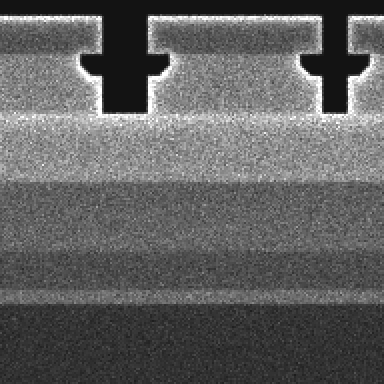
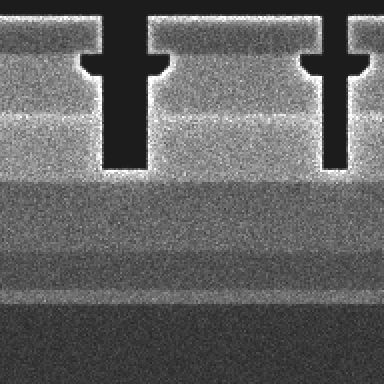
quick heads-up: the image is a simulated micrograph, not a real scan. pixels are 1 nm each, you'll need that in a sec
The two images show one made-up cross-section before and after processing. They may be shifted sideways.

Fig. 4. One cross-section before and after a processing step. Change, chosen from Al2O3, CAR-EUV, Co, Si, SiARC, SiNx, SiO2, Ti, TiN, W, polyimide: W removed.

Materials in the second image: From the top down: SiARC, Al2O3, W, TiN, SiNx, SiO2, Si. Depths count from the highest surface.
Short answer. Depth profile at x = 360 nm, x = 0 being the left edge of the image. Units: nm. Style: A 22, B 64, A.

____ SiARC 38, empty 20, Al2O3 40, W 68, TiN 70, SiNx 38, SiO2 14, Si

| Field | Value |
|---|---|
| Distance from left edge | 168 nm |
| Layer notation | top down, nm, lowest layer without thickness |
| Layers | SiARC 38, empty 12, Al2O3 48, W 68, TiN 70, SiNx 38, SiO2 14, Si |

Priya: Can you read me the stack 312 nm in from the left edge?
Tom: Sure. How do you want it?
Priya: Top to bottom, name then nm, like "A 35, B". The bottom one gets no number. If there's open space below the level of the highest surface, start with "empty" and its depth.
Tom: SiARC 38, empty 22, Al2O3 38, W 68, TiN 70, SiNx 38, SiO2 14, Si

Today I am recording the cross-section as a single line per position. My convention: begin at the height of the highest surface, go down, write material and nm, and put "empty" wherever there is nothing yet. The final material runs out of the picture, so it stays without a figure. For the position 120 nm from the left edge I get empty 154, W 12, TiN 70, SiNx 38, SiO2 14, Si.